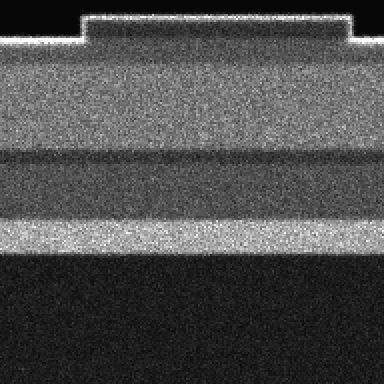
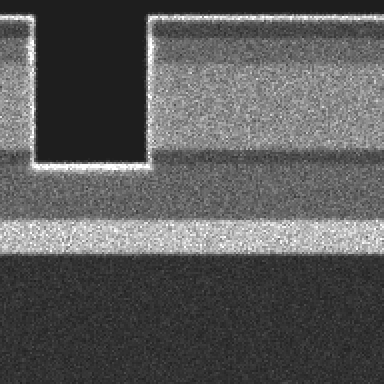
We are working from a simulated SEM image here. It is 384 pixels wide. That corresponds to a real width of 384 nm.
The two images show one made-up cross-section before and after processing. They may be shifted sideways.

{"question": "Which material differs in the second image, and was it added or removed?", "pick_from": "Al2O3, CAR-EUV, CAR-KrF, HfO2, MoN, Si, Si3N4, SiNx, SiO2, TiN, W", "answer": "Al2O3 and TiN and W, removed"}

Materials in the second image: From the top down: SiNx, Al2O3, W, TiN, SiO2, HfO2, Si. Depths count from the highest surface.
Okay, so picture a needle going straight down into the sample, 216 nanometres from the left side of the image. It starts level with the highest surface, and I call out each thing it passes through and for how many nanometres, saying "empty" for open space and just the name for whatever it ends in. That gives SiNx 22, Al2O3 26, W 86, TiN 14, SiO2 56, HfO2 34, Si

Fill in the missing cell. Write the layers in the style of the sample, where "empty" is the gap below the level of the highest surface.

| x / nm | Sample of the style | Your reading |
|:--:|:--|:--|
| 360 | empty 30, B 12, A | SiNx 22, Al2O3 26, W 86, TiN 14, SiO2 56, HfO2 34, Si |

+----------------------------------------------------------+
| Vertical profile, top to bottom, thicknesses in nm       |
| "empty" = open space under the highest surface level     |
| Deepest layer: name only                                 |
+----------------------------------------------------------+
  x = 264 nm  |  SiNx 22, Al2O3 26, W 86, TiN 14, SiO2 56, HfO2 34, Si